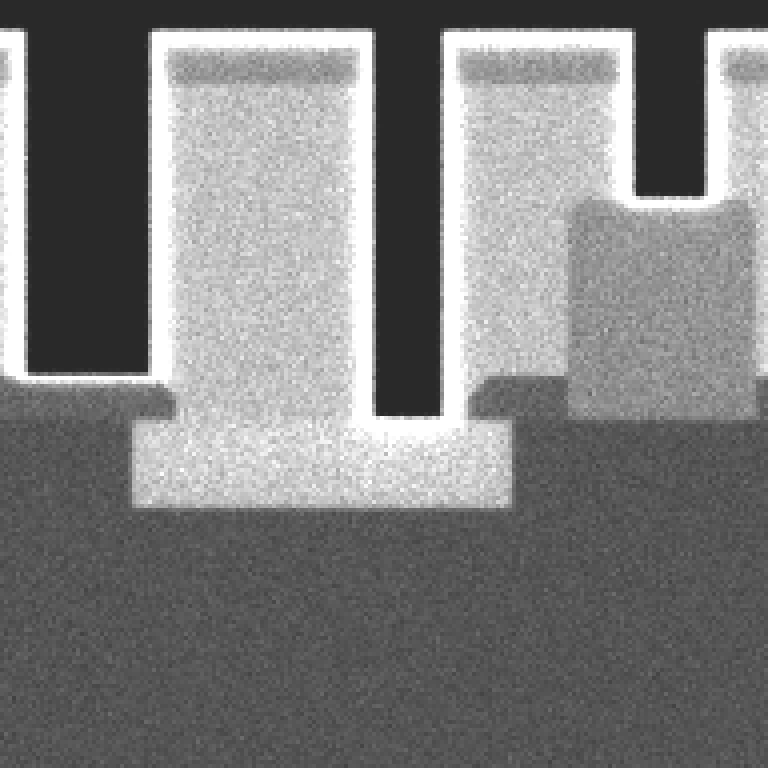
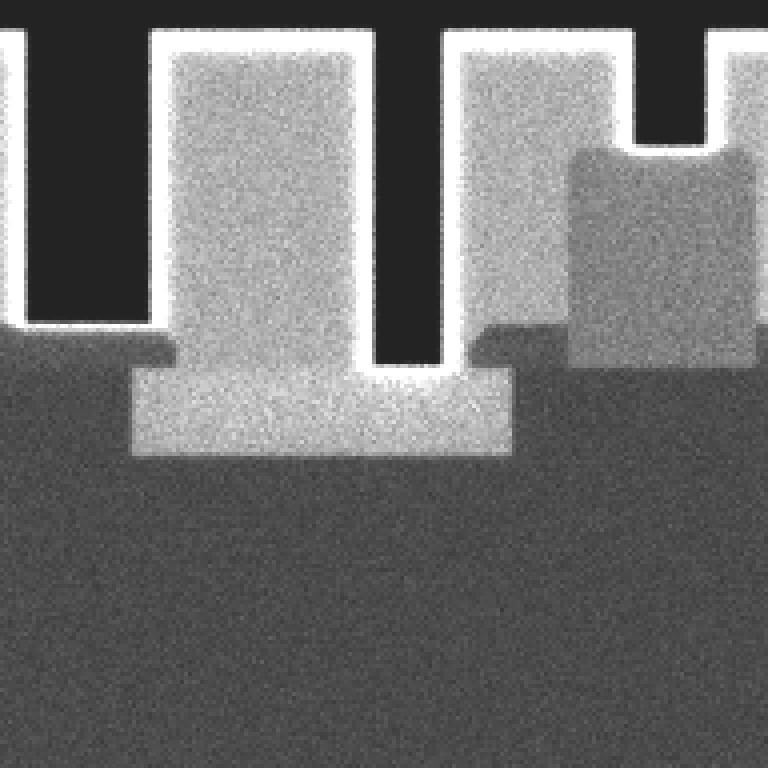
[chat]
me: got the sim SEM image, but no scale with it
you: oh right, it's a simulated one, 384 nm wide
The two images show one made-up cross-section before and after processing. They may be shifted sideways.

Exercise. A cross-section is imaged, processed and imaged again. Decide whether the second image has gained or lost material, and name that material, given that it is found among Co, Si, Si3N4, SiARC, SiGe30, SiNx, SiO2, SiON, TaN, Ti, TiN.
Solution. removed: SiARC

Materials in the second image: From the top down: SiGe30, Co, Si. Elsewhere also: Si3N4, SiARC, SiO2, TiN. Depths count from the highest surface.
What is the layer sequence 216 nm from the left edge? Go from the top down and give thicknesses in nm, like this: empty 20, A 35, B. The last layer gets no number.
empty 168, Co 44, Si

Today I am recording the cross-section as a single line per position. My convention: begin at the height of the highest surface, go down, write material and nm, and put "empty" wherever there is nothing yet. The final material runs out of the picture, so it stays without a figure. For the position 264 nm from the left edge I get SiO2 146, SiGe30 22, Si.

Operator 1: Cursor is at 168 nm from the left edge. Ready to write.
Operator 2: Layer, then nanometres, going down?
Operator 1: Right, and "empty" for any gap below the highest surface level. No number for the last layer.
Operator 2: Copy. SiO2 168, Co 44, Si